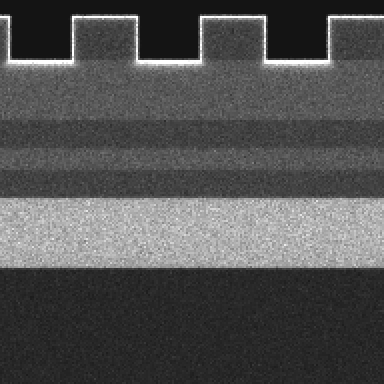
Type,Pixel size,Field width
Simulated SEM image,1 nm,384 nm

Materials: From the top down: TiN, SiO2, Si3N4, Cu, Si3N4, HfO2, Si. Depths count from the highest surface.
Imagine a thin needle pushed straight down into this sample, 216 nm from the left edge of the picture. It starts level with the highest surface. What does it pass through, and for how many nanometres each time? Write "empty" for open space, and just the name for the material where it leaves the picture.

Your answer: TiN 44, SiO2 60, Si3N4 28, Cu 22, Si3N4 28, HfO2 70, Si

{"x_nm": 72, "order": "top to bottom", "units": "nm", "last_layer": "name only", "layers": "TiN 44, SiO2 60, Si3N4 28, Cu 22, Si3N4 28, HfO2 70, Si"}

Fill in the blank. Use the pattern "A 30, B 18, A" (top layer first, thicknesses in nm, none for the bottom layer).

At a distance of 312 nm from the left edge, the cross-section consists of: empty 44, SiO2 60, Si3N4 28, Cu 22, Si3N4 28, HfO2 70, Si